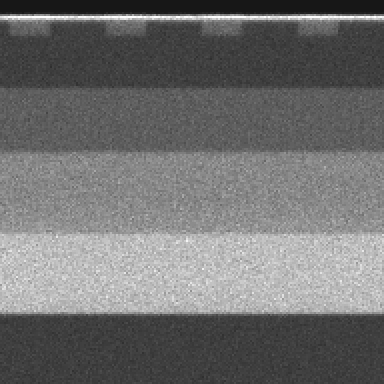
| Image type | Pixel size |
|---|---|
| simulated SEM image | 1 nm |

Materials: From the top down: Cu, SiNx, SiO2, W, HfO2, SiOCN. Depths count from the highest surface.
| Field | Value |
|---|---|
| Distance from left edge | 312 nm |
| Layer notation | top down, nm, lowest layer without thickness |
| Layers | Cu 20, SiNx 52, SiO2 64, W 82, HfO2 80, SiOCN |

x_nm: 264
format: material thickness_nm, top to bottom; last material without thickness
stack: SiNx 72, SiO2 64, W 82, HfO2 80, SiOCN